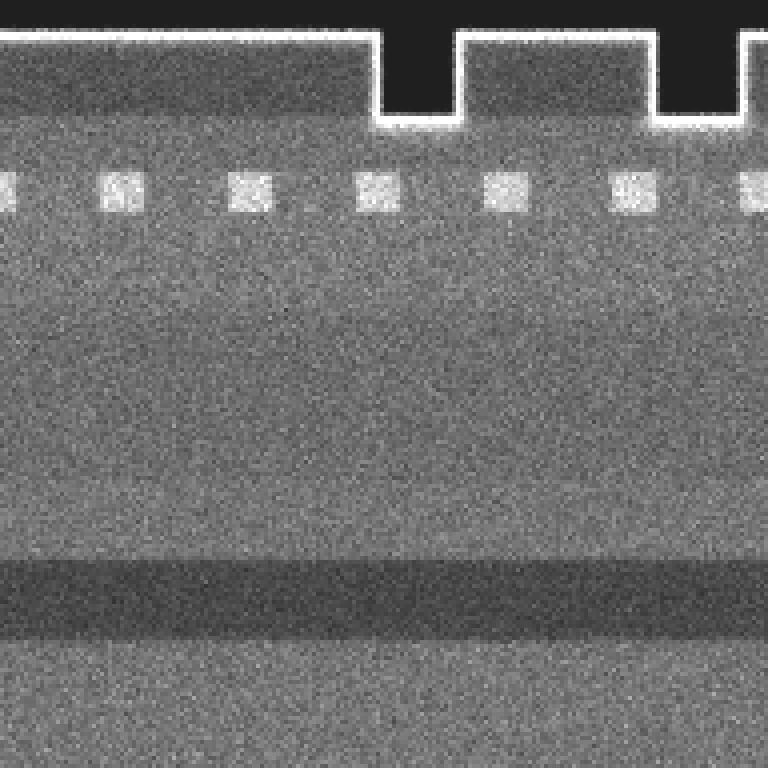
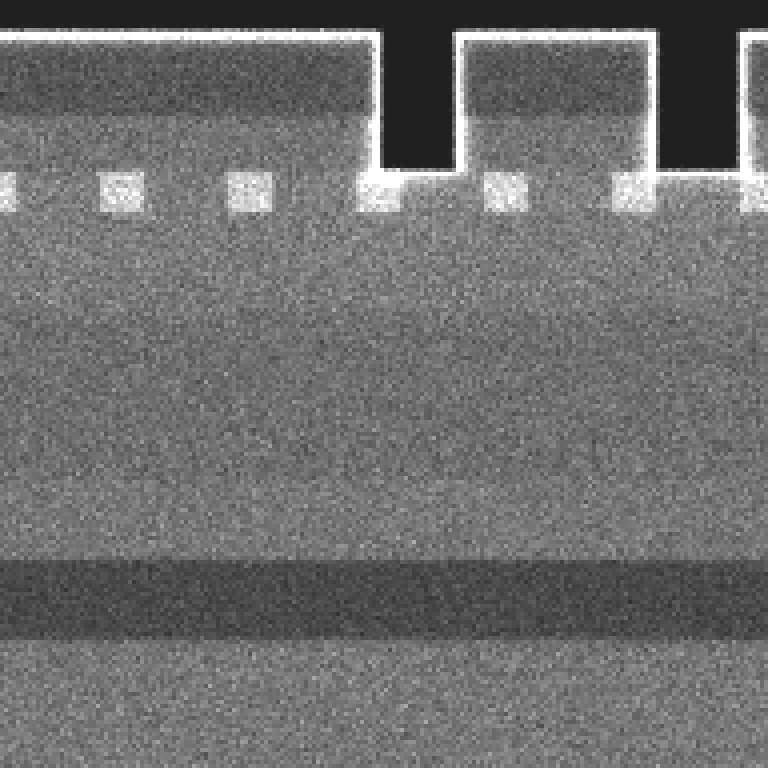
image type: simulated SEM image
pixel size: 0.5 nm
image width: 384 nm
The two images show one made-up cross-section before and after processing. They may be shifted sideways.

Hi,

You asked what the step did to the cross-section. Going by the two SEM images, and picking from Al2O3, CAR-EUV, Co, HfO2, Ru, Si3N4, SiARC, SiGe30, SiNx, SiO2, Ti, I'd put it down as SiO2, removed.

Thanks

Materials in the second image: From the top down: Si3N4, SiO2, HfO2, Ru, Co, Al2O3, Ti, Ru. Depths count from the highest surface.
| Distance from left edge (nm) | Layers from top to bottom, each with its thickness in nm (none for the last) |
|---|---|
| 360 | empty 70, Ru 70, Co 84, Al2O3 40, Ti 40, Ru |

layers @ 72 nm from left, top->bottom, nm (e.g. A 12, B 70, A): Si3N4 42, SiO2 28, Ru 70, Co 84, Al2O3 40, Ti 40, Ru